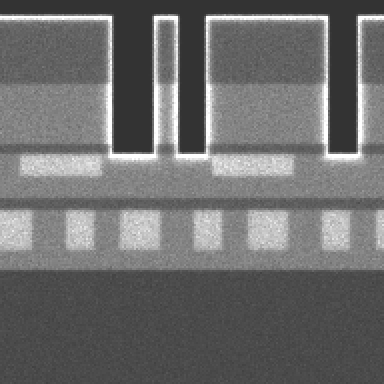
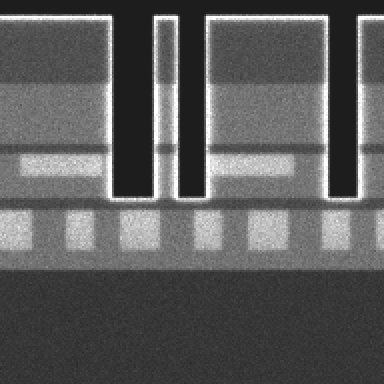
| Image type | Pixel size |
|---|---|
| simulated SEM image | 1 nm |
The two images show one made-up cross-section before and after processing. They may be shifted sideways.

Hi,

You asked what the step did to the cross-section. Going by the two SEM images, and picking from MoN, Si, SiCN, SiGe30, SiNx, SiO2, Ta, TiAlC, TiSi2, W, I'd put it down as SiO2, removed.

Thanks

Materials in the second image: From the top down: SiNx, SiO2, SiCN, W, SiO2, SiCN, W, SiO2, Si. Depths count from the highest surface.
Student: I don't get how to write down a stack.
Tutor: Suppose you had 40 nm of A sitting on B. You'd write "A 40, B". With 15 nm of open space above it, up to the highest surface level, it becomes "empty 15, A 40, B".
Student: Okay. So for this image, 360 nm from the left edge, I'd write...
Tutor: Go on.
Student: SiNx 68, SiO2 60, SiCN 10, SiO2 44, SiCN 12, SiO2 60, Si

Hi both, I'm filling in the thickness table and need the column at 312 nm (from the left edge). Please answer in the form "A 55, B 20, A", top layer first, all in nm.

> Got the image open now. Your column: SiNx 68, SiO2 60, SiCN 10, SiO2 44, SiCN 12, SiO2 60, Si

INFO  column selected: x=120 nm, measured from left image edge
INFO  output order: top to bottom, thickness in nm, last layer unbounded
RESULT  empty 182, SiCN 12, W 40, SiO2 20, Si